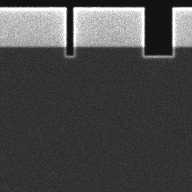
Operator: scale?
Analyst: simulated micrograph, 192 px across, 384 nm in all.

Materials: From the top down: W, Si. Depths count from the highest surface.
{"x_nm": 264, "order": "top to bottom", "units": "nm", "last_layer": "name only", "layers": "W 78, Si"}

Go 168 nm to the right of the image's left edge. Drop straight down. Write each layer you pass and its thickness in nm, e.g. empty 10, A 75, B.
W 78, Si